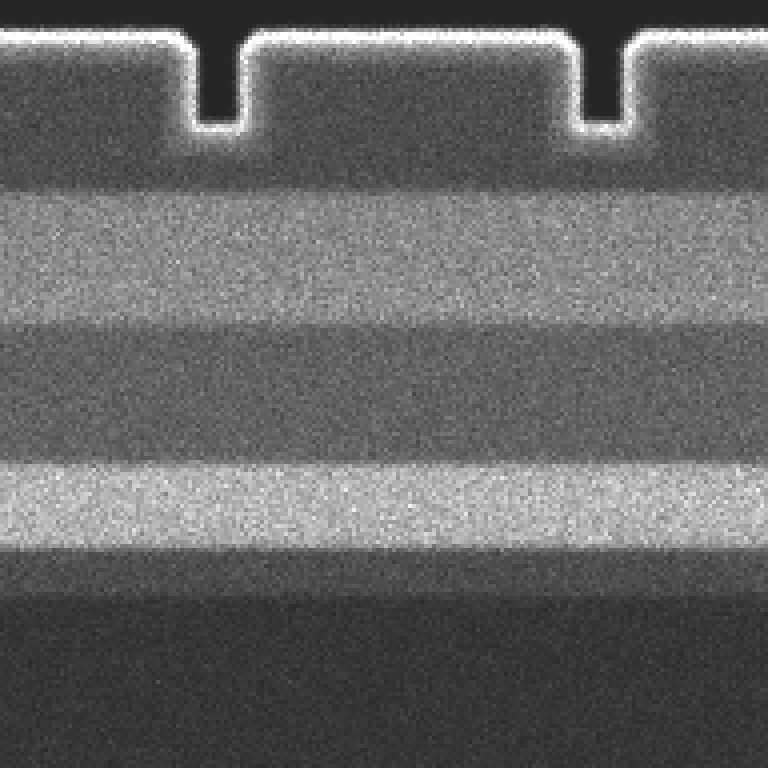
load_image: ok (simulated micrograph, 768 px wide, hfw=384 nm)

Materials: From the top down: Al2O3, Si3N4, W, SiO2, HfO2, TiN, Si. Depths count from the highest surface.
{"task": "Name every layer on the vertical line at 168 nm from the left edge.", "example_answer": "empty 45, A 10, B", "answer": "Al2O3 16, Si3N4 64, W 66, SiO2 70, HfO2 42, TiN 24, Si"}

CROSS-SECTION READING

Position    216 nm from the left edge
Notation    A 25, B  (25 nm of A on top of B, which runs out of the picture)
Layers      Al2O3 16, Si3N4 64, W 66, SiO2 70, HfO2 42, TiN 24, Si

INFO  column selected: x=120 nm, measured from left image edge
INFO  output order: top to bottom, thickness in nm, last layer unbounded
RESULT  empty 8, Al2O3 54, Si3N4 18, W 66, SiO2 70, HfO2 42, TiN 24, Si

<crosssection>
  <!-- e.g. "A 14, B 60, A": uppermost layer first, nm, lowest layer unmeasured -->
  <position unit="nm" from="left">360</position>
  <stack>Al2O3 16, Si3N4 64, W 66, SiO2 70, HfO2 42, TiN 24, Si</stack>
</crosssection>